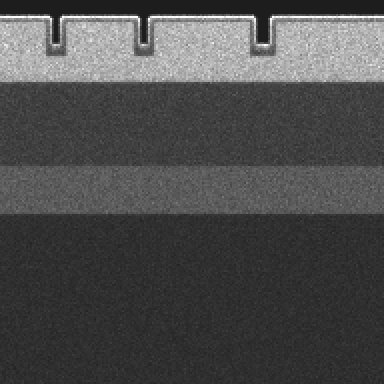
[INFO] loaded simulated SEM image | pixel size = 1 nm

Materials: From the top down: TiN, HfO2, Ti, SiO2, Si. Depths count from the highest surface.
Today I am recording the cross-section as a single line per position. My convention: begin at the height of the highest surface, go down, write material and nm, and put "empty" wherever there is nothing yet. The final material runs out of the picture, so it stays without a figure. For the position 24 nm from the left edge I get TiN 6, HfO2 60, Ti 84, SiO2 48, Si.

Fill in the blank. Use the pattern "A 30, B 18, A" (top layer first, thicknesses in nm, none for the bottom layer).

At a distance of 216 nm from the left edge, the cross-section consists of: TiN 6, HfO2 60, Ti 84, SiO2 48, Si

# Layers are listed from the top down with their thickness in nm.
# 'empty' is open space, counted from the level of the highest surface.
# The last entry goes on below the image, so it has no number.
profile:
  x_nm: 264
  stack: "empty 28, TiN 12, HfO2 26, Ti 84, SiO2 48, Si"